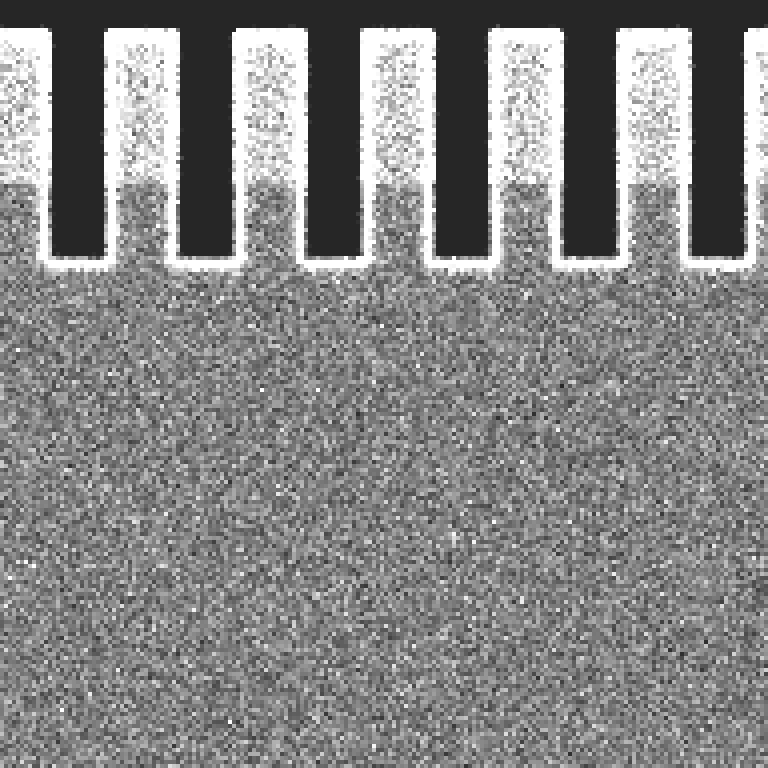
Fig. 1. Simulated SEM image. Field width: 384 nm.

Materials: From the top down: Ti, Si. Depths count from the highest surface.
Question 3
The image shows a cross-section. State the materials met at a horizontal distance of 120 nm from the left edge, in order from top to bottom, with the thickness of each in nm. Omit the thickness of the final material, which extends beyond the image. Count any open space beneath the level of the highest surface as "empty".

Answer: Ti 76, Si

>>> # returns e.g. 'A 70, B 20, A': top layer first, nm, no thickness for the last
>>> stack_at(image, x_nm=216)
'empty 114, Si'